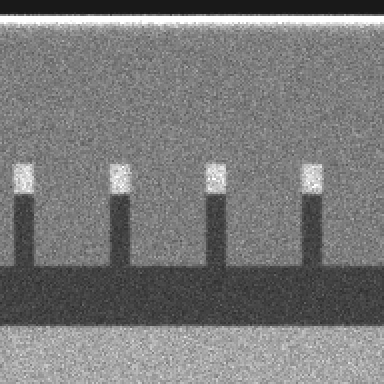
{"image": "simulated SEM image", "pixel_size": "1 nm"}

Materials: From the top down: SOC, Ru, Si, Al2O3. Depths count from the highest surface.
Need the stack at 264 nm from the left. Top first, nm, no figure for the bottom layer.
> SOC 250, Si 60, Al2O3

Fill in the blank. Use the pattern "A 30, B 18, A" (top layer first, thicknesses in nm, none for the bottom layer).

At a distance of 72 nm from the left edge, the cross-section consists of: SOC 250, Si 60, Al2O3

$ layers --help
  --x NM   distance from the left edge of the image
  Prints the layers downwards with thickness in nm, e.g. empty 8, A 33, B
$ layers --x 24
SOC 148, Ru 30, Si 132, Al2O3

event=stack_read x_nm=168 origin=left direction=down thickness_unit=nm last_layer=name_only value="SOC 250, Si 60, Al2O3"